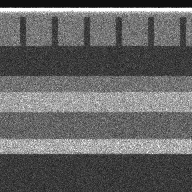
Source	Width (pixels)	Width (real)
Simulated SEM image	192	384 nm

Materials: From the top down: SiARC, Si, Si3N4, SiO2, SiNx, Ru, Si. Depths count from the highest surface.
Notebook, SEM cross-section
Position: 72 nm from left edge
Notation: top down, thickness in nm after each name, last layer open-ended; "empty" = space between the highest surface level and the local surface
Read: SiARC 76, Si 60, Si3N4 32, SiO2 40, SiNx 54, Ru 30, Si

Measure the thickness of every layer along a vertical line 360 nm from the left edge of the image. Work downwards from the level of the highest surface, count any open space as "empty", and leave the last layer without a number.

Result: SiARC 18, Si 118, Si3N4 32, SiO2 40, SiNx 54, Ru 30, Si